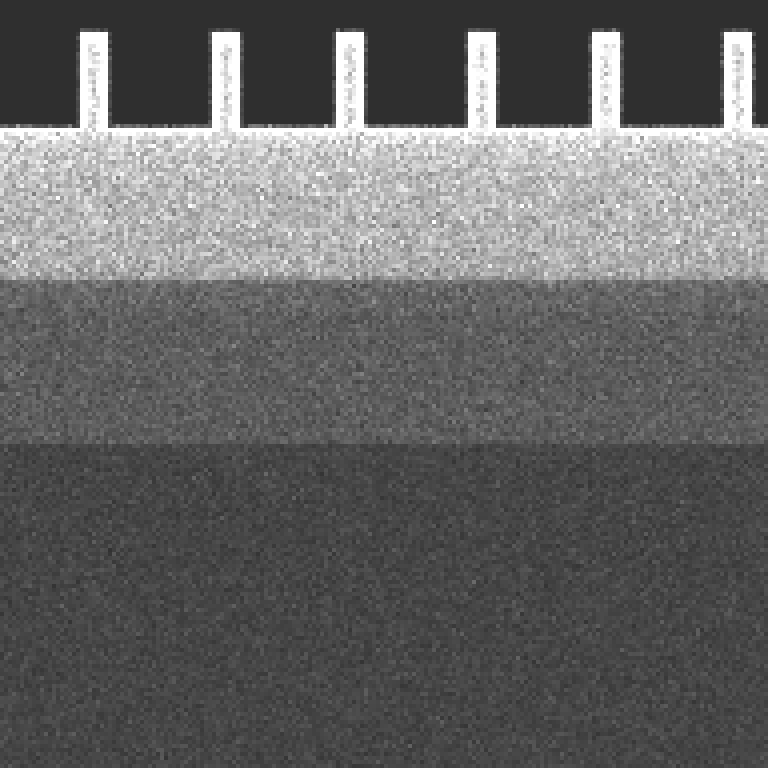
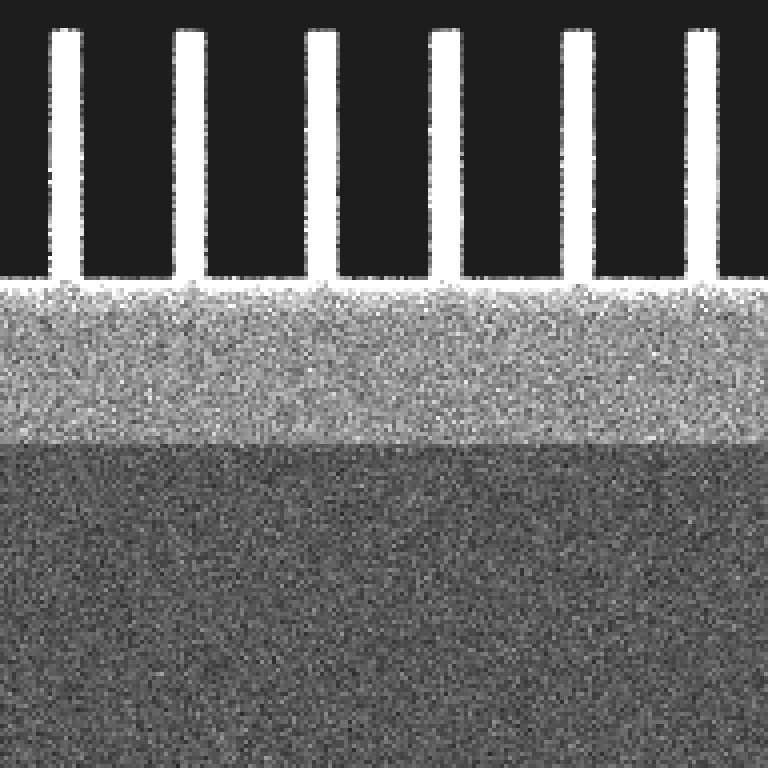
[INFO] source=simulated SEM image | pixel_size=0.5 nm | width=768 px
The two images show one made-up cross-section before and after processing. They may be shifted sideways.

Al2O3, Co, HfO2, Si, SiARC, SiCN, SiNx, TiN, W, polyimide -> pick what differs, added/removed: W removed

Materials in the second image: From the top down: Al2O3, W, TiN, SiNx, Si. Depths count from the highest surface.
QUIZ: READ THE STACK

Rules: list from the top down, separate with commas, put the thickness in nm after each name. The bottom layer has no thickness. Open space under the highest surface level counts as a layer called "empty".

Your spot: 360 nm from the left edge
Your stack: empty 124, TiN 16, SiNx 66, Si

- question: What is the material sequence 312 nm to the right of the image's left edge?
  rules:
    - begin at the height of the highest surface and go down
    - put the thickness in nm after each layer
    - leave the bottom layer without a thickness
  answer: empty 124, TiN 16, SiNx 66, Si